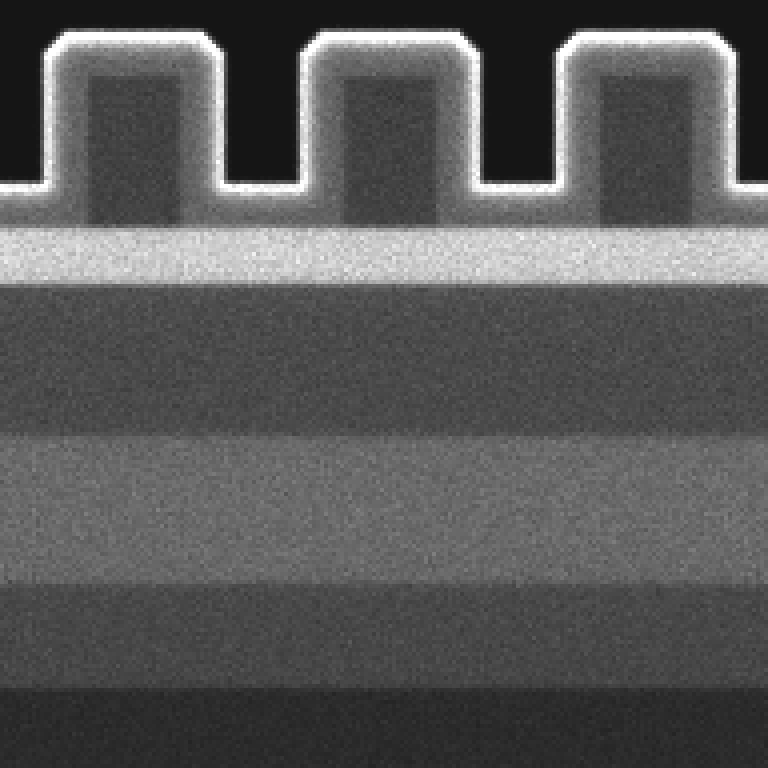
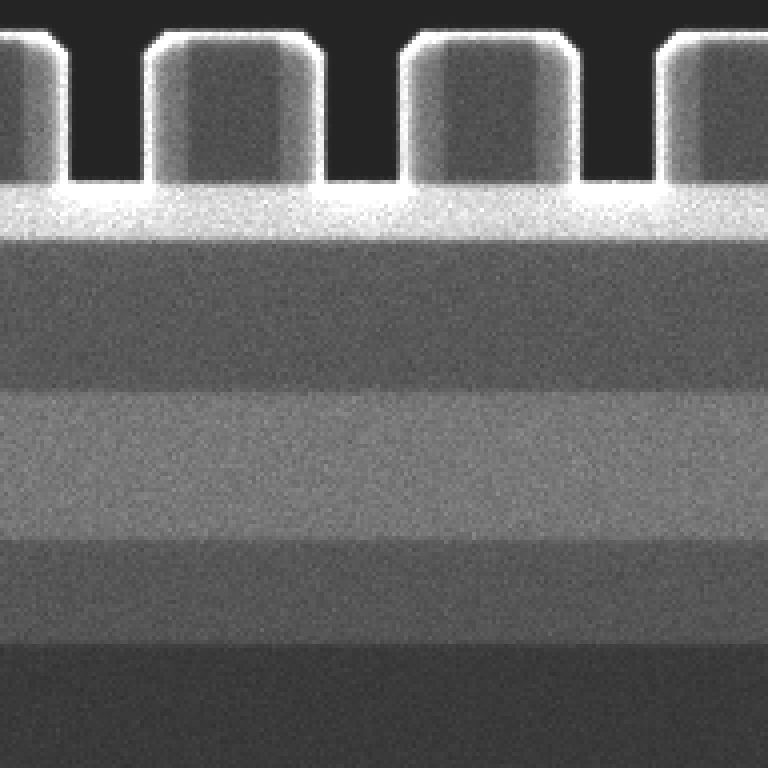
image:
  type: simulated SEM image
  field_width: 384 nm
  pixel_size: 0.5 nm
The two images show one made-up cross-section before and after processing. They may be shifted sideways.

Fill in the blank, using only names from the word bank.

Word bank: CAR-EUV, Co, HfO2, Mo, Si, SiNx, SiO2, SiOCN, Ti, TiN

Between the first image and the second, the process removed SiO2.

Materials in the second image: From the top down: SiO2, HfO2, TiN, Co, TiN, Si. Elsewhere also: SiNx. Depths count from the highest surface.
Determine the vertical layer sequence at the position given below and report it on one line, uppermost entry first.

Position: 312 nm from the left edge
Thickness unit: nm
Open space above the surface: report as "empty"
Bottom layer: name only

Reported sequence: empty 76, HfO2 28, TiN 76, Co 74, TiN 52, Si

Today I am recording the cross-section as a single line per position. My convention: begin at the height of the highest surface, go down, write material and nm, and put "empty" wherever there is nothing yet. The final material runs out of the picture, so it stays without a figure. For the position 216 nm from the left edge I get SiO2 76, HfO2 28, TiN 76, Co 74, TiN 52, Si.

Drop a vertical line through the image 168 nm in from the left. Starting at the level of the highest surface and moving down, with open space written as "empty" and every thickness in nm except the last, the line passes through empty 76, HfO2 28, TiN 76, Co 74, TiN 52, Si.